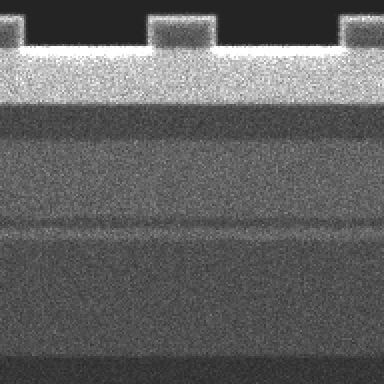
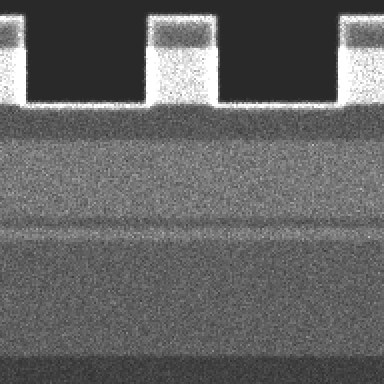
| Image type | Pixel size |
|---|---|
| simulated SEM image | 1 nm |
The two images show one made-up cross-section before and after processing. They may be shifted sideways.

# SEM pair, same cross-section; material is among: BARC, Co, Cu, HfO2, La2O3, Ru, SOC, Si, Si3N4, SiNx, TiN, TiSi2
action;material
removed;HfO2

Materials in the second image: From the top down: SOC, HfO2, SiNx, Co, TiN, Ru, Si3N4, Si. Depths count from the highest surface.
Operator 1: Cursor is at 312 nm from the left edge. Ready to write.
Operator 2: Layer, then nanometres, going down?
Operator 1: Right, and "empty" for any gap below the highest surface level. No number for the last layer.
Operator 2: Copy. empty 88, SiNx 36, Co 78, TiN 10, Ru 12, Si3N4 116, Si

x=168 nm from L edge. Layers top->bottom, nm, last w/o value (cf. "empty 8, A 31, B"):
SOC 32, HfO2 56, SiNx 36, Co 78, TiN 10, Ru 12, Si3N4 116, Si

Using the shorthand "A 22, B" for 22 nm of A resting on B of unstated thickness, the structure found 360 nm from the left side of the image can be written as SOC 32, HfO2 56, SiNx 36, Co 78, TiN 10, Ru 12, Si3N4 116, Si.